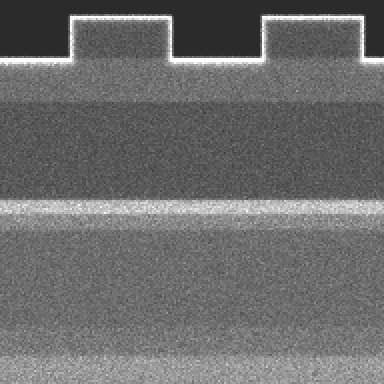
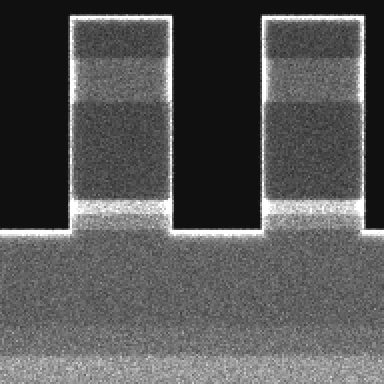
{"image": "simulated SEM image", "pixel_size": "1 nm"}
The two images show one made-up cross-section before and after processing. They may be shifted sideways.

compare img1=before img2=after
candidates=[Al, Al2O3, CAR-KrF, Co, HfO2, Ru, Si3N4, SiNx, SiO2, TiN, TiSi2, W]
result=removed:Al2O3 and HfO2 and Ru and TiN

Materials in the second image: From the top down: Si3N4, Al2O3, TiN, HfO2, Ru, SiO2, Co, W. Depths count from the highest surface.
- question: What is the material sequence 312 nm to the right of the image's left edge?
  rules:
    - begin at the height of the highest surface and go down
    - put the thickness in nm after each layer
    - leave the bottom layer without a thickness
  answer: Si3N4 42, Al2O3 44, TiN 98, HfO2 14, Ru 16, SiO2 96, Co 30, W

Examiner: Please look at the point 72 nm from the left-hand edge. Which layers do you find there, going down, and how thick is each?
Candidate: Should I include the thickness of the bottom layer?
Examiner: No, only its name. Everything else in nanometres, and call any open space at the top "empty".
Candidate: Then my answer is Si3N4 42, Al2O3 44, TiN 98, HfO2 14, Ru 16, SiO2 96, Co 30, W